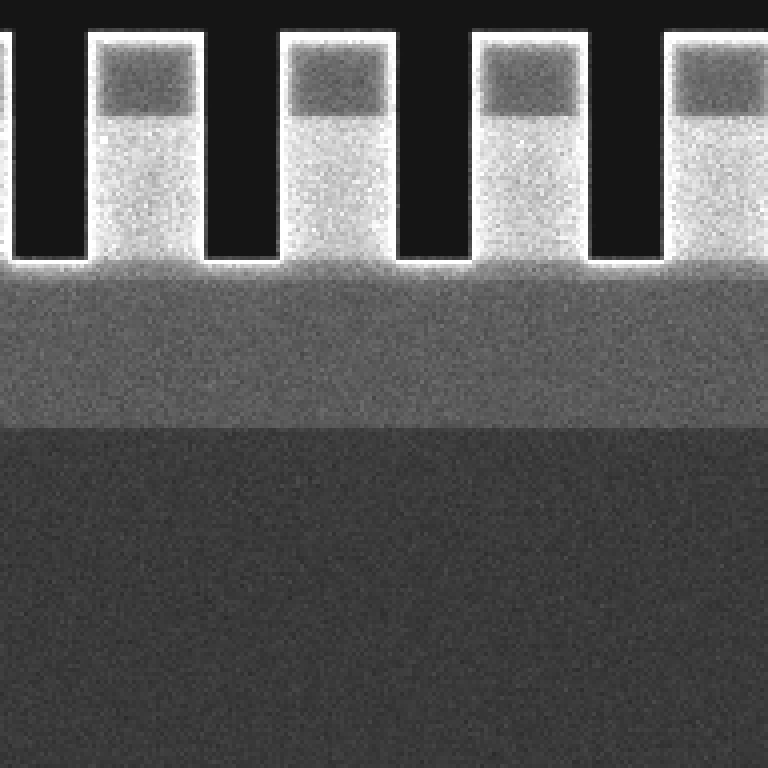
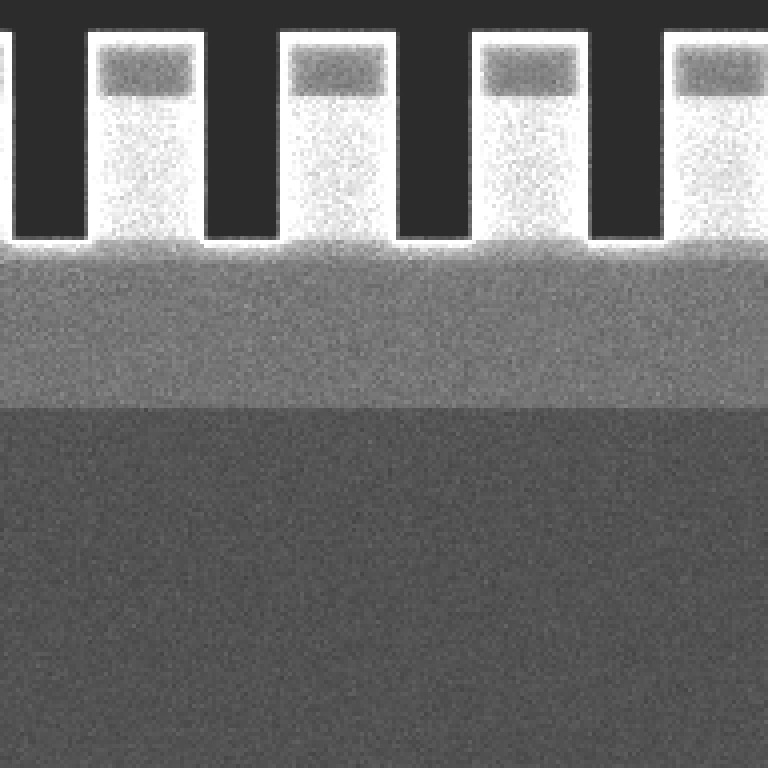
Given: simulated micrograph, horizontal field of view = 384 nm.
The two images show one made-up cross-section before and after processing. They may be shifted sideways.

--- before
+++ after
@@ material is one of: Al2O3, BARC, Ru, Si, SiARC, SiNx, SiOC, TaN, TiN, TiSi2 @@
SiARC removed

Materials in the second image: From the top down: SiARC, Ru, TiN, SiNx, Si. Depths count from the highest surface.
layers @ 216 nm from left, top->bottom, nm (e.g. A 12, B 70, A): empty 104, TiN 10, SiNx 74, Si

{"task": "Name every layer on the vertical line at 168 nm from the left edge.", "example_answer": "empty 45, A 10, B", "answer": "SiARC 32, Ru 72, TiN 10, SiNx 74, Si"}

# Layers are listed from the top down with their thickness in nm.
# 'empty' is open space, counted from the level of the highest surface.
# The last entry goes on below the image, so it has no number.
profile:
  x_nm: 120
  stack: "empty 104, TiN 10, SiNx 74, Si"